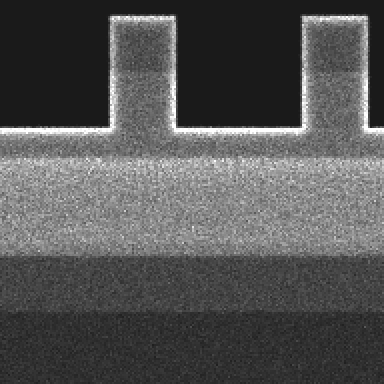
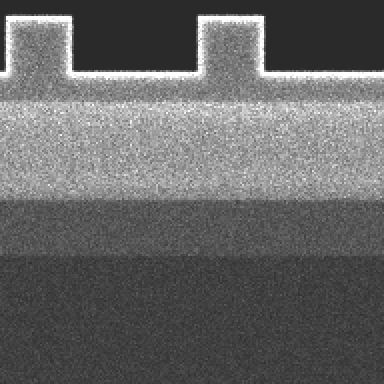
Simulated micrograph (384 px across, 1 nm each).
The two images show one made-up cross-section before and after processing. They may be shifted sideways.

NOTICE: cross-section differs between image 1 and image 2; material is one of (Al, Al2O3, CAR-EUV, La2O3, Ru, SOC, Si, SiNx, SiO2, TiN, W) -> removed: SOC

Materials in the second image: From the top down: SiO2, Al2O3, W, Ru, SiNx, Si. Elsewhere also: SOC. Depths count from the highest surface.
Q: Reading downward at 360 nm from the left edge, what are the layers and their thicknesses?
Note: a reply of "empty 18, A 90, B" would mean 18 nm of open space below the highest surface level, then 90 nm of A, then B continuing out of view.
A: empty 56, Al2O3 30, W 86, Ru 12, SiNx 56, Si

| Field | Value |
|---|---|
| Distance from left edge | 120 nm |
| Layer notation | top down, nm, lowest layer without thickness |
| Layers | empty 56, Al2O3 30, W 86, Ru 12, SiNx 56, Si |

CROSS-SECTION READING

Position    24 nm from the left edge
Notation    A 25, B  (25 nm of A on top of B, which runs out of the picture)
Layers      SiO2 56, Al2O3 30, W 86, Ru 12, SiNx 56, Si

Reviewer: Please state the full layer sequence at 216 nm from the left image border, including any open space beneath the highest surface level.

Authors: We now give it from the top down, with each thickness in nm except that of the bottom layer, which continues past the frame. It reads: SiO2 56, Al2O3 30, W 86, Ru 12, SiNx 56, Si